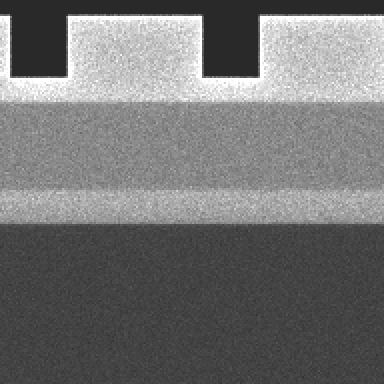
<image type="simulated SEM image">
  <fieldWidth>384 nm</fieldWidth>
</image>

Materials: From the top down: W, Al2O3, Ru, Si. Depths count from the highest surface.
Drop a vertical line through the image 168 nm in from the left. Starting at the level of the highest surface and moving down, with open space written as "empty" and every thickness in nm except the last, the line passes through W 86, Al2O3 88, Ru 34, Si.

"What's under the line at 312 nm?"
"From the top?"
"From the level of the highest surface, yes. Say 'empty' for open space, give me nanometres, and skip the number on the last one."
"W 86, Al2O3 88, Ru 34, Si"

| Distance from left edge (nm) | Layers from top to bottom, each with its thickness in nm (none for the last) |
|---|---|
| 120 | W 86, Al2O3 88, Ru 34, Si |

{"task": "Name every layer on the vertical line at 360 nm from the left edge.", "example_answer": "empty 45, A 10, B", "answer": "W 86, Al2O3 88, Ru 34, Si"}